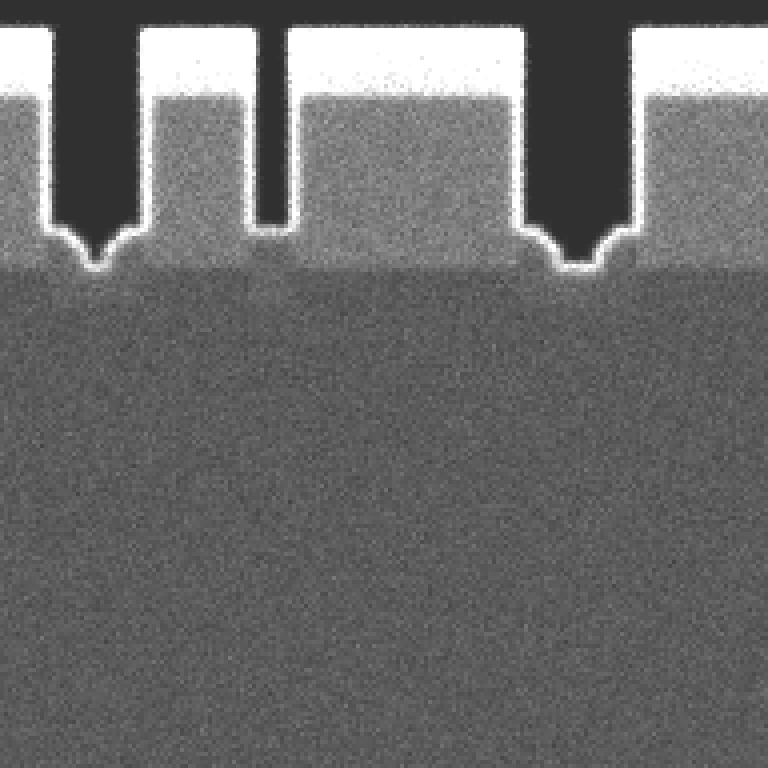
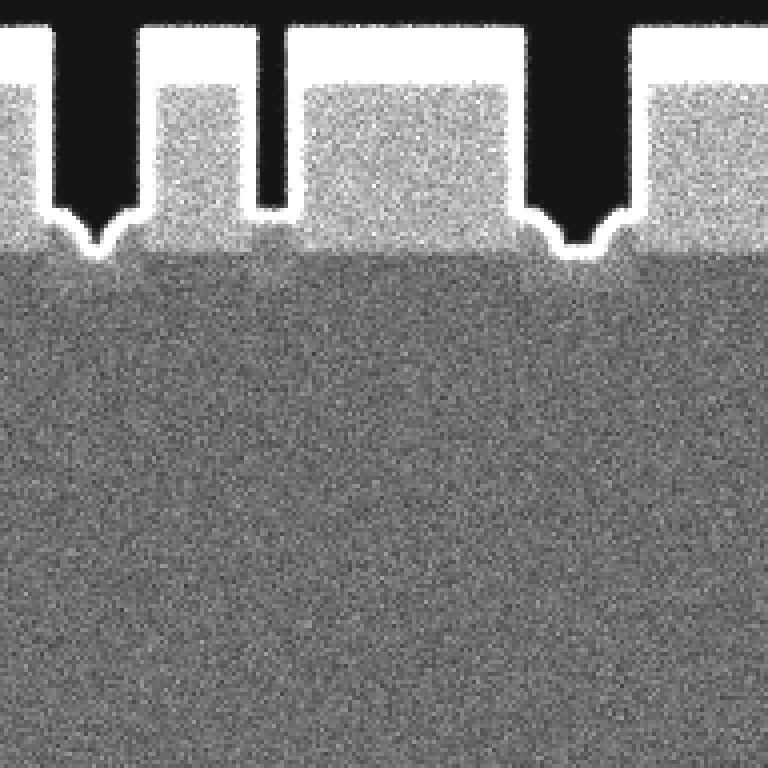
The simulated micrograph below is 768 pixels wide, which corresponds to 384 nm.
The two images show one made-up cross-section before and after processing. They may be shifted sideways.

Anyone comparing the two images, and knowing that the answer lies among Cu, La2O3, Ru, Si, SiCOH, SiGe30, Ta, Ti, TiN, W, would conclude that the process removed W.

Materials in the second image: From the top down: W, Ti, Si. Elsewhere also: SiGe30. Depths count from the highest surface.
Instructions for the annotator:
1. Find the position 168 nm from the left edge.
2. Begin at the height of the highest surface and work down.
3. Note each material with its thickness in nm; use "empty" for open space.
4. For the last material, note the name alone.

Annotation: W 24, Ti 86, Si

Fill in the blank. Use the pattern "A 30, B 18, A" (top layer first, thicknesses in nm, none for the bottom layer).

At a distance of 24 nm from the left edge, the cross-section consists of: empty 90, SiGe30 38, Si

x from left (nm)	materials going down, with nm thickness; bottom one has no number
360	W 24, Ti 86, Si